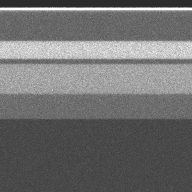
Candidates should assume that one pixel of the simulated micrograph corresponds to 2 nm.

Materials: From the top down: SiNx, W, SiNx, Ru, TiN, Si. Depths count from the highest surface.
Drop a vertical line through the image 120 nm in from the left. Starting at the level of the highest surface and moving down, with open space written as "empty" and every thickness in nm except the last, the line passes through SiNx 66, W 36, SiNx 10, Ru 60, TiN 50, Si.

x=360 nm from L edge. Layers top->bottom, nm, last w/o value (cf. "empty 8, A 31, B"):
SiNx 66, W 36, SiNx 10, Ru 60, TiN 50, Si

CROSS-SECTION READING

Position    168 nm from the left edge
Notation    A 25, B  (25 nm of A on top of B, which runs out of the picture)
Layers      SiNx 66, W 36, SiNx 10, Ru 60, TiN 50, Si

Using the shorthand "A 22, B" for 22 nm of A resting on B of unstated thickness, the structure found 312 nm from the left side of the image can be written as SiNx 66, W 36, SiNx 10, Ru 60, TiN 50, Si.